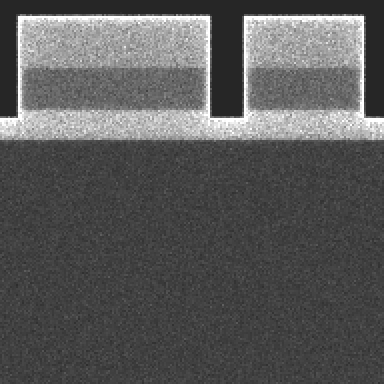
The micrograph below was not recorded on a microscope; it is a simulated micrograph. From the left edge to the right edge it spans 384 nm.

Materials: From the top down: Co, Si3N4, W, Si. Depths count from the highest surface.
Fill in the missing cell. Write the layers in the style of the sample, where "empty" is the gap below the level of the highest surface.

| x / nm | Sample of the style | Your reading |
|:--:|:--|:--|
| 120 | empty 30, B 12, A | Co 52, Si3N4 42, W 30, Si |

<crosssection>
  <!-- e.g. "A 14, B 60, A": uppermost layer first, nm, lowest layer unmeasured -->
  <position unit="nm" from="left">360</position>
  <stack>Co 52, Si3N4 42, W 30, Si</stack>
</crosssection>